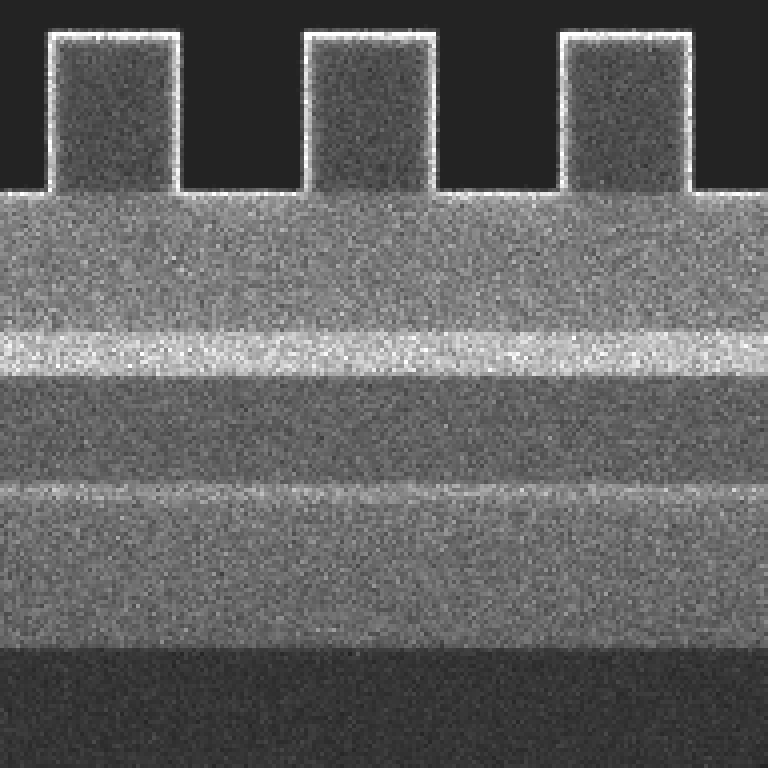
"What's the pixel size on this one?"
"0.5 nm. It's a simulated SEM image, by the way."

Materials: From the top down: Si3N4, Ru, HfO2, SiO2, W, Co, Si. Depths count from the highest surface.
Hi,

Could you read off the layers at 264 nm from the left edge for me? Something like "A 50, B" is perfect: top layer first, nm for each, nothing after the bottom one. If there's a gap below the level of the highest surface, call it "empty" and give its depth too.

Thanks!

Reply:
empty 80, Ru 70, HfO2 22, SiO2 54, W 8, Co 74, Si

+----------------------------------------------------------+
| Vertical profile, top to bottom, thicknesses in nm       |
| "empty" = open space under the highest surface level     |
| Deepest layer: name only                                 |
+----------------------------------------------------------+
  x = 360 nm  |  empty 80, Ru 70, HfO2 22, SiO2 54, W 8, Co 74, Si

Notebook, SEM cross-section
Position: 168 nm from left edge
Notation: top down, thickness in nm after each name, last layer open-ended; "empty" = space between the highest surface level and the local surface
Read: Si3N4 80, Ru 70, HfO2 22, SiO2 54, W 8, Co 74, Si